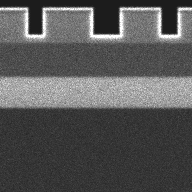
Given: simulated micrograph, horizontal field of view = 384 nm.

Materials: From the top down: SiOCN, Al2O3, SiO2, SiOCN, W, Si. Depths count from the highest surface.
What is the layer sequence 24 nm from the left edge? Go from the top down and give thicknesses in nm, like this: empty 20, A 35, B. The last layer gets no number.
SiOCN 10, Al2O3 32, SiO2 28, SiOCN 68, W 62, Si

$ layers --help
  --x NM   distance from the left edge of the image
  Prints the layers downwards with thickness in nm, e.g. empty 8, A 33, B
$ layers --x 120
SiOCN 10, Al2O3 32, SiO2 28, SiOCN 68, W 62, Si